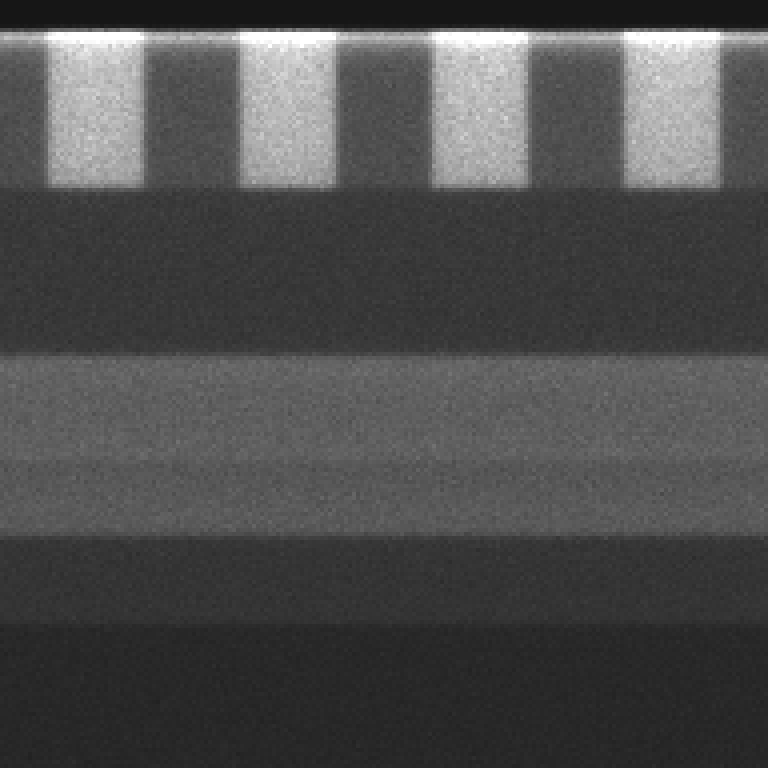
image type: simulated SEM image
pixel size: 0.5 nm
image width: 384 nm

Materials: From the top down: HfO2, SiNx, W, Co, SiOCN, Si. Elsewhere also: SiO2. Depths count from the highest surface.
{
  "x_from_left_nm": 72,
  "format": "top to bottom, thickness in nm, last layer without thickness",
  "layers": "SiO2 78, SiNx 84, W 52, Co 38, SiOCN 44, Si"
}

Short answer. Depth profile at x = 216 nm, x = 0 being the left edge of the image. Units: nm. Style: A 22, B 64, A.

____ HfO2 78, SiNx 84, W 52, Co 38, SiOCN 44, Si